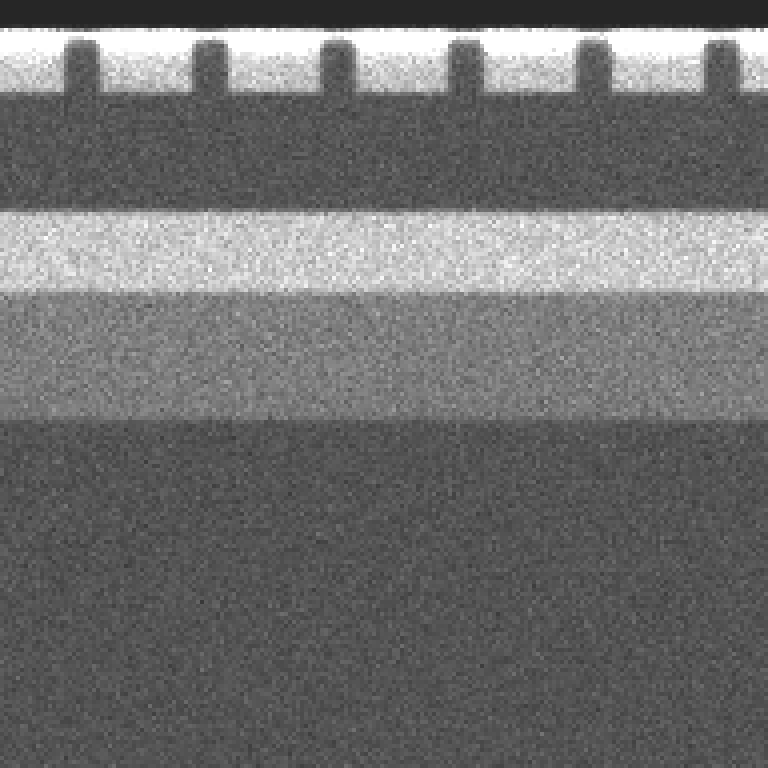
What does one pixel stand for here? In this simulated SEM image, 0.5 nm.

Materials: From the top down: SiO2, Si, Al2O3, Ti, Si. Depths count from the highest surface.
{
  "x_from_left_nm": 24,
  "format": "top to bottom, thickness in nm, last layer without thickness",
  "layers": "SiO2 30, Si 60, Al2O3 40, Ti 64, Si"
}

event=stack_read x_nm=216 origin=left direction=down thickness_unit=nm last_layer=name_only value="SiO2 30, Si 60, Al2O3 40, Ti 64, Si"